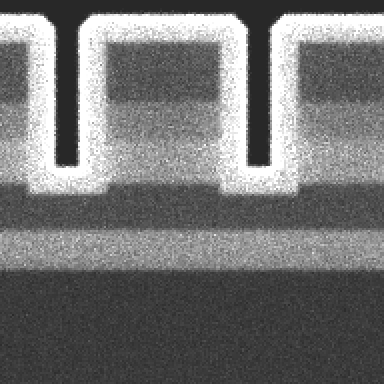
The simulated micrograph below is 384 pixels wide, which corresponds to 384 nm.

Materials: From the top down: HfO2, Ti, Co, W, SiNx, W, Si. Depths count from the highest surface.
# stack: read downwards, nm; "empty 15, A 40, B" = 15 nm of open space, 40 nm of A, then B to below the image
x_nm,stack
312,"HfO2 26, Ti 60, Co 38, W 44, SiNx 46, W 40, Si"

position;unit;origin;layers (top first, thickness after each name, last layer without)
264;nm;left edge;empty 152, HfO2 26, SiNx 36, W 40, Si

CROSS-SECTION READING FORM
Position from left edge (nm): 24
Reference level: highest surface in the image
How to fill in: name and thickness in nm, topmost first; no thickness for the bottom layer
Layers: HfO2 26, Ti 60, Co 38, W 44, SiNx 46, W 40, Si